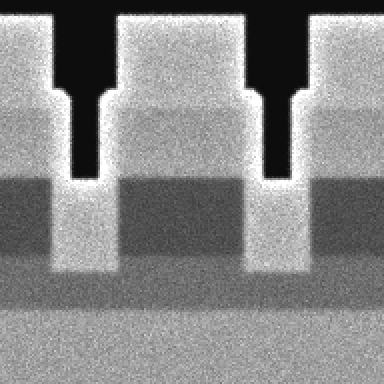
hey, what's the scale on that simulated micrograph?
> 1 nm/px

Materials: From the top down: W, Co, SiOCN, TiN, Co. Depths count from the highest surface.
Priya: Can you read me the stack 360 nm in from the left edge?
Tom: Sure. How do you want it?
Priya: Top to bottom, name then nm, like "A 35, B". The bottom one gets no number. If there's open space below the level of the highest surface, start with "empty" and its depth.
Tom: W 92, Co 70, SiOCN 78, TiN 54, Co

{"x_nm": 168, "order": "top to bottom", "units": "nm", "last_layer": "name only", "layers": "W 92, Co 70, SiOCN 78, TiN 54, Co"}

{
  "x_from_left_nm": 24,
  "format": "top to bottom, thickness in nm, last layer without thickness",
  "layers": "W 92, Co 70, SiOCN 78, TiN 54, Co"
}